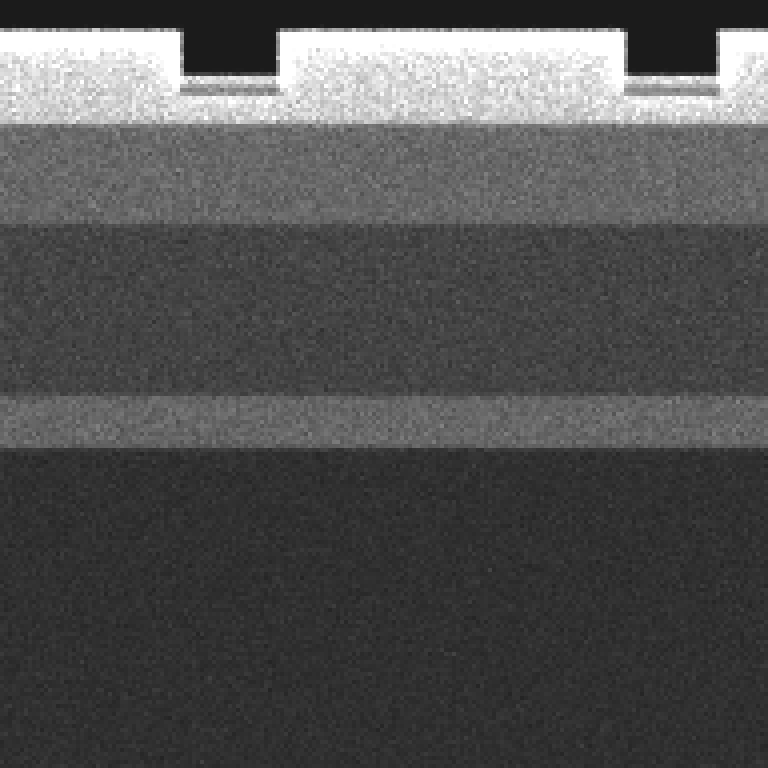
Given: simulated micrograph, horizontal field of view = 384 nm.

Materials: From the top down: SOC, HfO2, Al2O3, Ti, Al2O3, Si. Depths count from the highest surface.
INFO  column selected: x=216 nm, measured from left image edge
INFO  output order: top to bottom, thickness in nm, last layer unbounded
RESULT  HfO2 46, Al2O3 50, Ti 86, Al2O3 26, Si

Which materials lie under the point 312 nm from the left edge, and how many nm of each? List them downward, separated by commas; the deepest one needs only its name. empty 22, SOC 10, HfO2 14, Al2O3 50, Ti 86, Al2O3 26, Si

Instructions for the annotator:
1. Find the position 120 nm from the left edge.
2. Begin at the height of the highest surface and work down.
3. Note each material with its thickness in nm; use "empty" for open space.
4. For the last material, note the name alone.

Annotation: empty 22, SOC 10, HfO2 14, Al2O3 50, Ti 86, Al2O3 26, Si